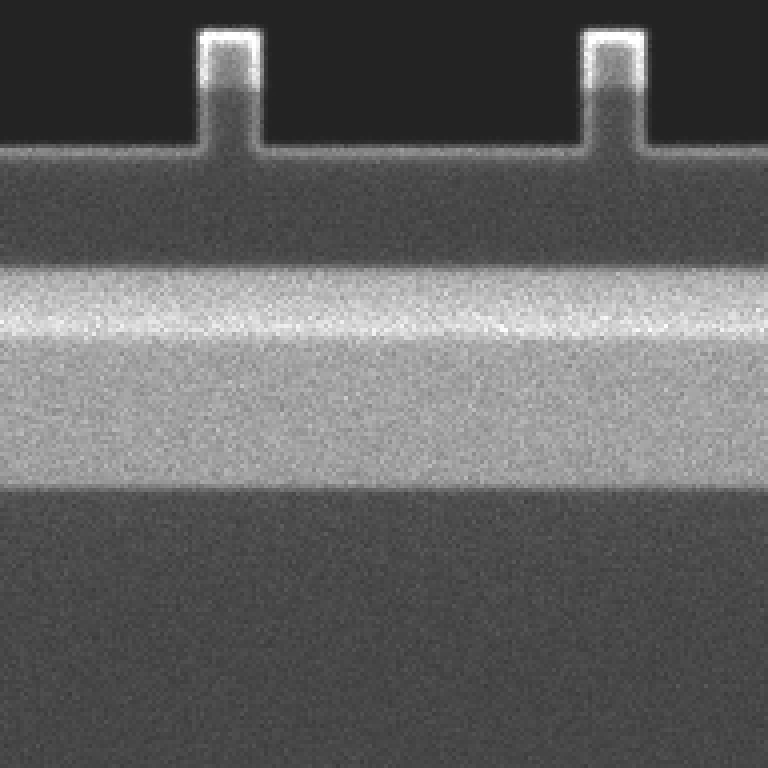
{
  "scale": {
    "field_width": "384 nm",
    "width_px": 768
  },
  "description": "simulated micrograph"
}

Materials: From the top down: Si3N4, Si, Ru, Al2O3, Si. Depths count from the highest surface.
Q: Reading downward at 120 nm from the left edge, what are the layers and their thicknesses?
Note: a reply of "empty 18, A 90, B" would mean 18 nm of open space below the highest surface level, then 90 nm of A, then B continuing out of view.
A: Si3N4 28, Si 90, Ru 34, Al2O3 76, Si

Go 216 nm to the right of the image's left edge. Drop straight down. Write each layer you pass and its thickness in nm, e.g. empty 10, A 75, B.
empty 58, Si 60, Ru 34, Al2O3 76, Si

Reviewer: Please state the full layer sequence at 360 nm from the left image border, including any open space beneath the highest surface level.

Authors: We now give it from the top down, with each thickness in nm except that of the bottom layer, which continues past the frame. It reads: empty 58, Si 60, Ru 34, Al2O3 76, Si